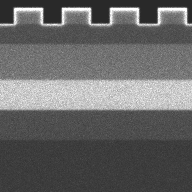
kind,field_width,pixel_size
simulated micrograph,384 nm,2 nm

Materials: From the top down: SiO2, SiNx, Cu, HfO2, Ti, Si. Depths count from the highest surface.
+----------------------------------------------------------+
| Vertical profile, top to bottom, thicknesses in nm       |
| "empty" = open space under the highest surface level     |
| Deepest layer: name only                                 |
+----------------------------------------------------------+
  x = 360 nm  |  SiO2 32, SiNx 40, Cu 72, HfO2 60, Ti 60, Si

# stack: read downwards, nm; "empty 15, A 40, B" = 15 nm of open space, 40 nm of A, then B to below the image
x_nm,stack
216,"empty 32, SiNx 40, Cu 72, HfO2 60, Ti 60, Si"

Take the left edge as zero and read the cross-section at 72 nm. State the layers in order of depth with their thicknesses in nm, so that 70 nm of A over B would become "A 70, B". SiO2 32, SiNx 40, Cu 72, HfO2 60, Ti 60, Si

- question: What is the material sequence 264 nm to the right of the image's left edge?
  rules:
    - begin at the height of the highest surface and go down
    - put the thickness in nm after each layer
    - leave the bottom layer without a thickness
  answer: SiO2 32, SiNx 40, Cu 72, HfO2 60, Ti 60, Si